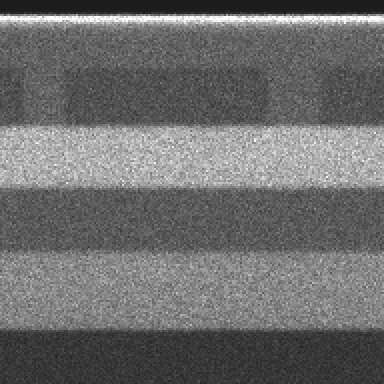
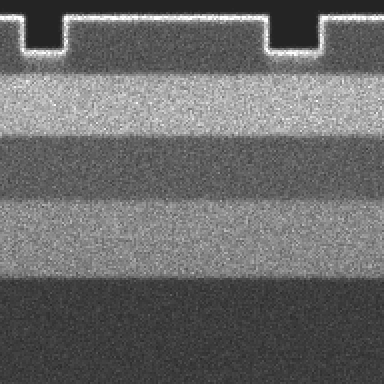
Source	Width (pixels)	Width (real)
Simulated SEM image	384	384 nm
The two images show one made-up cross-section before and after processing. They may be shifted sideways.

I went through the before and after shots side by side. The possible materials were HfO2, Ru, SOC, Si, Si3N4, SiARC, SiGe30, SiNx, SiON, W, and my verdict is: removed, SOC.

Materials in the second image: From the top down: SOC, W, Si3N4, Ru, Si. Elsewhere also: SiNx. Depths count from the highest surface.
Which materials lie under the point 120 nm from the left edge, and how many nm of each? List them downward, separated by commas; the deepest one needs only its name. SiNx 58, W 62, Si3N4 64, Ru 78, Si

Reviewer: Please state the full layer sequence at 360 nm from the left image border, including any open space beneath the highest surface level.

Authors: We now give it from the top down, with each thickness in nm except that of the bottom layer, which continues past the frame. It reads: SiNx 58, W 62, Si3N4 64, Ru 78, Si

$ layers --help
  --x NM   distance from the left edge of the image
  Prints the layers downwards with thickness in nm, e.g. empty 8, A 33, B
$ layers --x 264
SiNx 58, W 62, Si3N4 64, Ru 78, Si